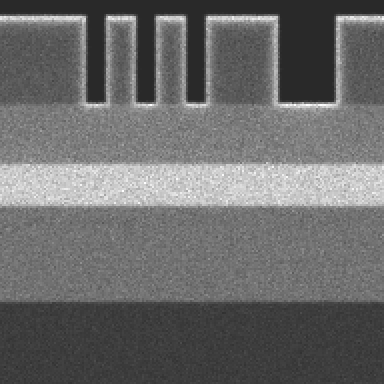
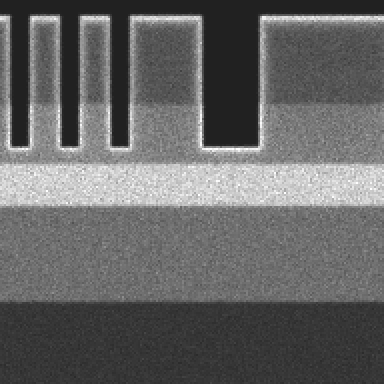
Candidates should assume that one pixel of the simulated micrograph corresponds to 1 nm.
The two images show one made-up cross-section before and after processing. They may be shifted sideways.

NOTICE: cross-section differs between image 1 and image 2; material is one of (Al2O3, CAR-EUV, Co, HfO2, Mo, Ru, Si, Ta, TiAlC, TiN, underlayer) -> removed: Ru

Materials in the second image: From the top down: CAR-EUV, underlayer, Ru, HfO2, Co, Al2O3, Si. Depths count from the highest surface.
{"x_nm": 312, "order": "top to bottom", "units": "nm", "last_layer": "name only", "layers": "CAR-EUV 52, underlayer 36, Ru 60, HfO2 42, Co 20, Al2O3 76, Si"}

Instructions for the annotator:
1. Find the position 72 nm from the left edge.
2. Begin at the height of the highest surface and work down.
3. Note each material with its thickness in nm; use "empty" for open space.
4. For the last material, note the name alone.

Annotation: empty 132, Ru 16, HfO2 42, Co 20, Al2O3 76, Si